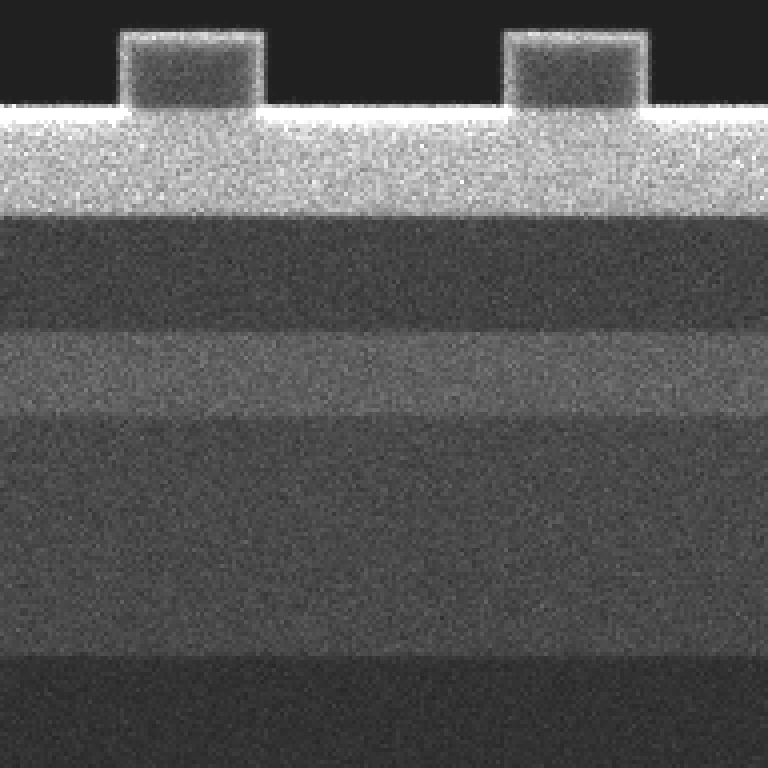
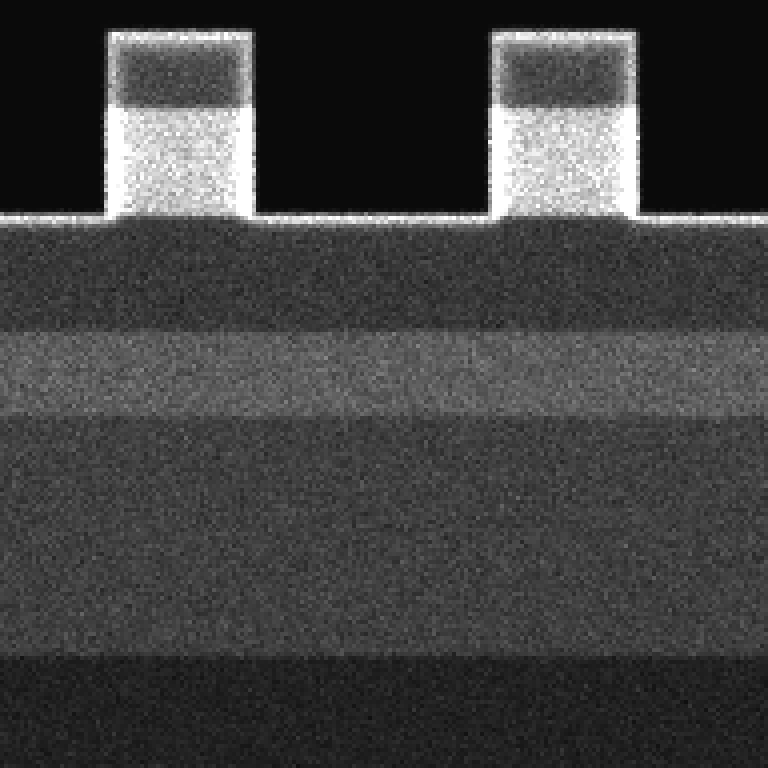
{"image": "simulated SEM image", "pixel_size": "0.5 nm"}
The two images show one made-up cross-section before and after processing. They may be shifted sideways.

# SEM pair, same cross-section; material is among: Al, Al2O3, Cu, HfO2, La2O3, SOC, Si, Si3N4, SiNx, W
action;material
removed;HfO2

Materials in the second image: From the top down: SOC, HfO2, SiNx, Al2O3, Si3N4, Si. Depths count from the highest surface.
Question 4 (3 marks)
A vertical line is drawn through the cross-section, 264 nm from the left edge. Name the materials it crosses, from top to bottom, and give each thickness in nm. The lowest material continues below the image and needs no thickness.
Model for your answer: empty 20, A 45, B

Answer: SOC 38, HfO2 54, SiNx 58, Al2O3 42, Si3N4 120, Si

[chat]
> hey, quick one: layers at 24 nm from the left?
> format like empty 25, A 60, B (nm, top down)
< empty 92, SiNx 58, Al2O3 42, Si3N4 120, Si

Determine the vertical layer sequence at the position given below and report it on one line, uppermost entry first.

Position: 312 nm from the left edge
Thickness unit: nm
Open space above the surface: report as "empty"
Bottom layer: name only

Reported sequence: SOC 38, HfO2 54, SiNx 58, Al2O3 42, Si3N4 120, Si